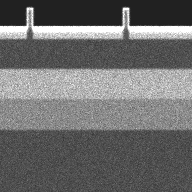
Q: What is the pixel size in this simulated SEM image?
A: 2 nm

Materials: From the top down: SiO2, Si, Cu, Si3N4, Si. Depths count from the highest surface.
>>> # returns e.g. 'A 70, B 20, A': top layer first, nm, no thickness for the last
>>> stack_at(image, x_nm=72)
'empty 38, SiO2 24, Si 60, Cu 60, Si3N4 62, Si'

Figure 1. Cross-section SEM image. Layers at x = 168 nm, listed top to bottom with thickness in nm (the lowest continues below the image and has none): empty 38, SiO2 24, Si 60, Cu 60, Si3N4 62, Si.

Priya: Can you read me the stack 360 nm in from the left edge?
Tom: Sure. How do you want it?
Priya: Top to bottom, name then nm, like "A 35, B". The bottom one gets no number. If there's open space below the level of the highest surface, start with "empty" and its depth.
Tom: empty 38, SiO2 24, Si 60, Cu 60, Si3N4 62, Si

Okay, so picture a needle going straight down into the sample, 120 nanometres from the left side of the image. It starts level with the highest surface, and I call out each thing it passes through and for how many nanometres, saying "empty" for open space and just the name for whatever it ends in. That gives empty 38, SiO2 24, Si 60, Cu 60, Si3N4 62, Si